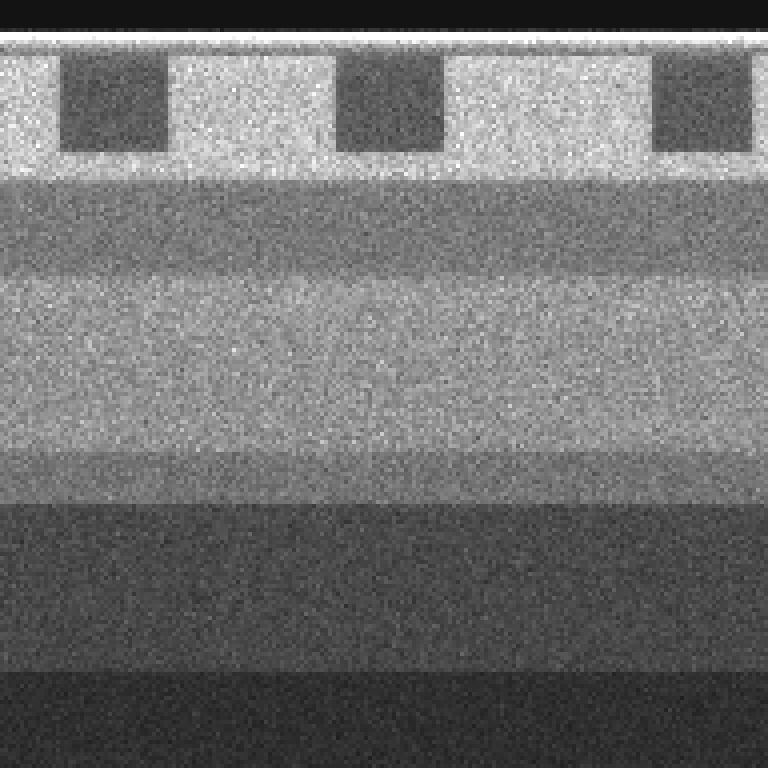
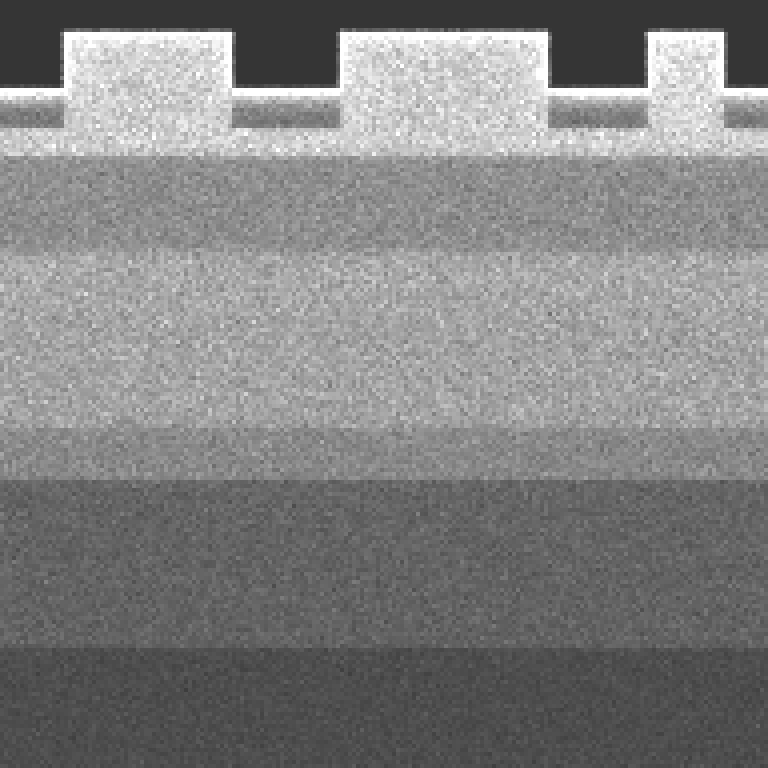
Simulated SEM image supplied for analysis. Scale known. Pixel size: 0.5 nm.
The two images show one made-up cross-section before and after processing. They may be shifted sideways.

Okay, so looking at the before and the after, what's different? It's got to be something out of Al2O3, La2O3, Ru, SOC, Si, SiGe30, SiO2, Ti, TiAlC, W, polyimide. SOC, removed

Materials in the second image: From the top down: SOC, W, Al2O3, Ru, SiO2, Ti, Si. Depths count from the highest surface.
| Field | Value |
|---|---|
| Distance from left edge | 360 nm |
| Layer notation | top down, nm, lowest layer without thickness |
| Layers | W 62, Al2O3 48, Ru 88, SiO2 26, Ti 84, Si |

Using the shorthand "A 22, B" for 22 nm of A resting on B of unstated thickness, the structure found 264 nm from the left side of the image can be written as W 62, Al2O3 48, Ru 88, SiO2 26, Ti 84, Si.